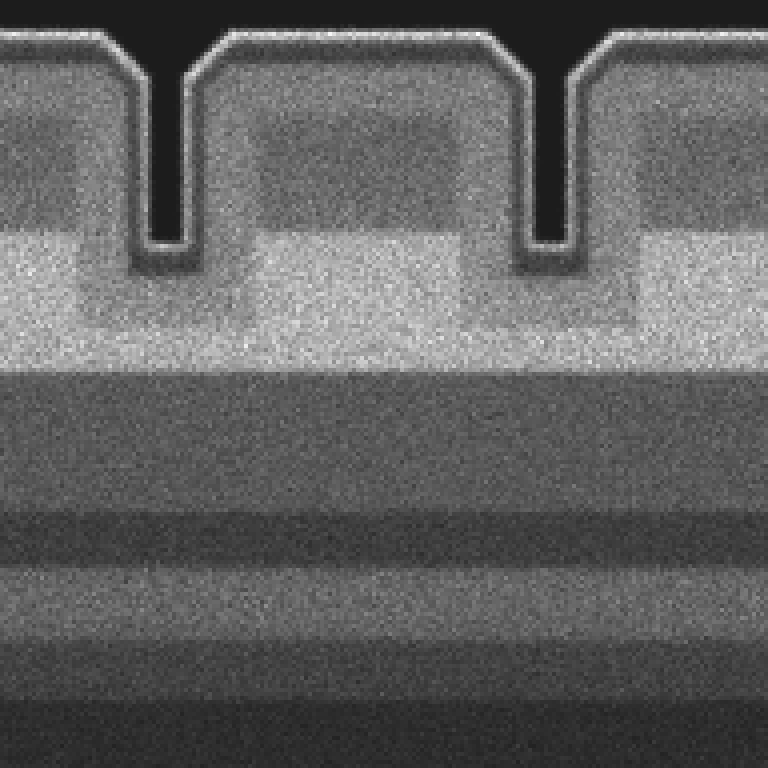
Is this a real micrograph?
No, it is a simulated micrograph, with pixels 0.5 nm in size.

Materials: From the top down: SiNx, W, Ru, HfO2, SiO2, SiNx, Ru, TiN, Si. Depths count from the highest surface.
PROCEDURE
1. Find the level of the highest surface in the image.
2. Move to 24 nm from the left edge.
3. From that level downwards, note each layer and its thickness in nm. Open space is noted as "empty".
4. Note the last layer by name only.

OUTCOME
SiNx 16, W 26, Ru 58, HfO2 70, SiO2 70, SiNx 28, Ru 36, TiN 30, Si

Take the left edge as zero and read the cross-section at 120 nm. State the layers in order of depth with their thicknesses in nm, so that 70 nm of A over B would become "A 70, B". SiNx 16, W 132, HfO2 22, SiO2 70, SiNx 28, Ru 36, TiN 30, Si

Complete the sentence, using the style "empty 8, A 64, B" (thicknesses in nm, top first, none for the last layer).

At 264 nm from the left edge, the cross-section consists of empty 22, SiNx 100, W 26, HfO2 22, SiO2 70, SiNx 28, Ru 36, TiN 30, Si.